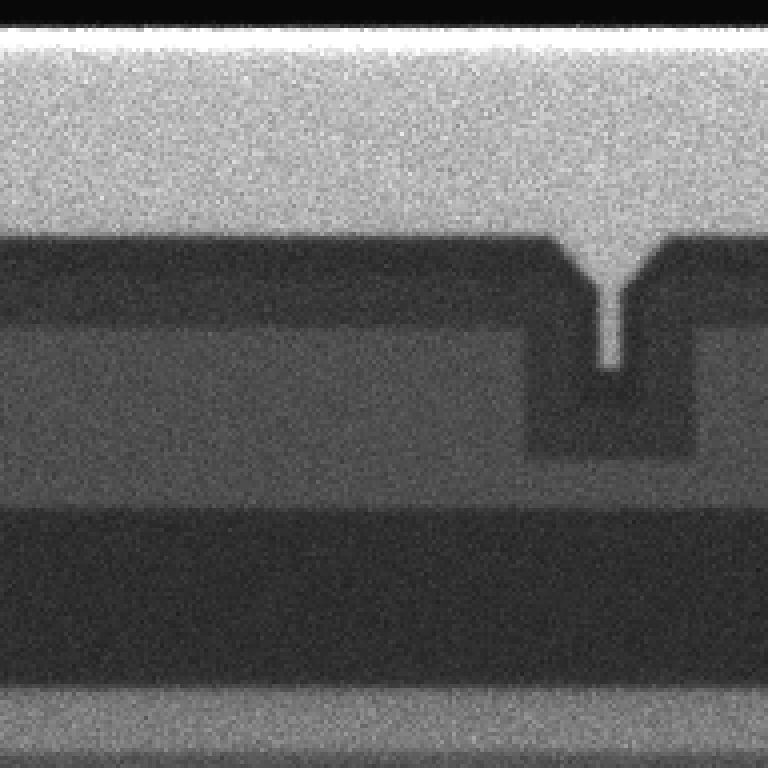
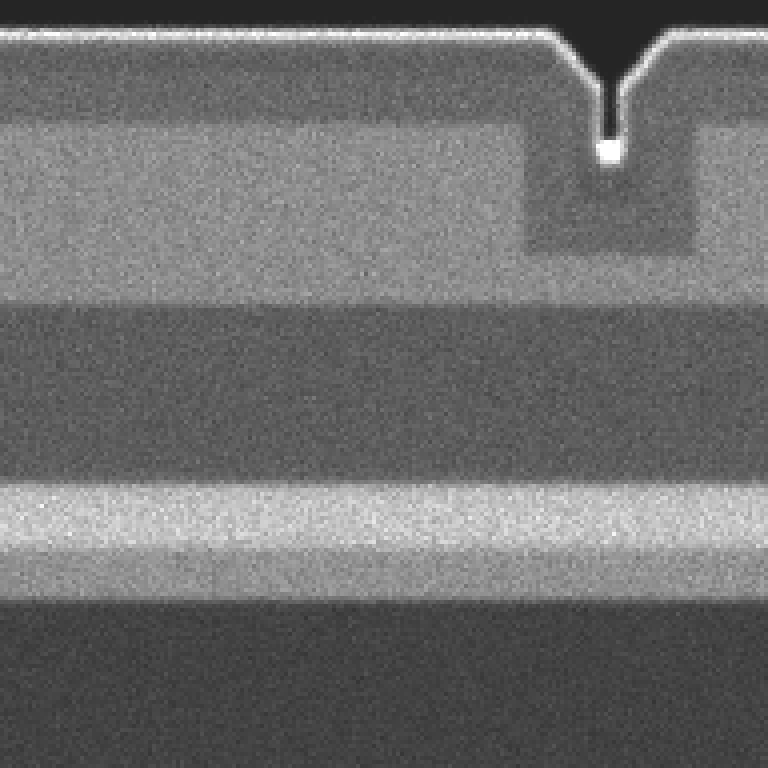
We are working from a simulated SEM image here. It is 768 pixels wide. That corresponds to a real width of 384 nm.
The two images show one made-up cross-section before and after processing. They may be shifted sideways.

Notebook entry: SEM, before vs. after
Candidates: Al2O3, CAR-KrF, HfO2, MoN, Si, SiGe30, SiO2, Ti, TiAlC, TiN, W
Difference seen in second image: HfO2 removed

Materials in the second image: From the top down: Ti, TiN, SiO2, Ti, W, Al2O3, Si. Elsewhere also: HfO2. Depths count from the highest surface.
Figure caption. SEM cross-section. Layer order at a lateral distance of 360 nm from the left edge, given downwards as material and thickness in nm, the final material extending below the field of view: Ti 20, TiN 26, SiO2 90, Ti 90, W 32, Al2O3 26, Si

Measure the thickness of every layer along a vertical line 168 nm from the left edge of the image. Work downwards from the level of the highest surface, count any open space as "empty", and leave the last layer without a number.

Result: Ti 20, TiN 26, SiO2 90, Ti 90, W 32, Al2O3 26, Si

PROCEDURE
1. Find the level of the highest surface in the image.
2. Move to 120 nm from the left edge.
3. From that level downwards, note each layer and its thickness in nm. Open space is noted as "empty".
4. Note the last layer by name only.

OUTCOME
Ti 20, TiN 26, SiO2 90, Ti 90, W 32, Al2O3 26, Si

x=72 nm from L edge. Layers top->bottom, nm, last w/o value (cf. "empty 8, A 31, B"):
Ti 20, TiN 26, SiO2 90, Ti 90, W 32, Al2O3 26, Si